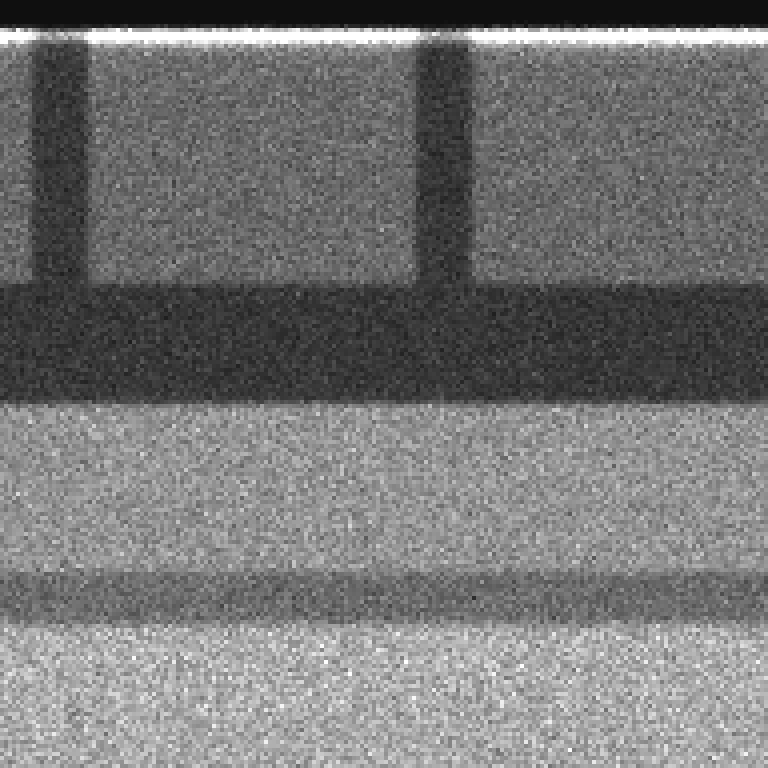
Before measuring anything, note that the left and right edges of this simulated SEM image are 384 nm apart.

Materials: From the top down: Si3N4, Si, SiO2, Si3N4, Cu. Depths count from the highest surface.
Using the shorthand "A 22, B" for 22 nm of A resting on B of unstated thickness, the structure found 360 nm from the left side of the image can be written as Si3N4 126, Si 60, SiO2 84, Si3N4 26, Cu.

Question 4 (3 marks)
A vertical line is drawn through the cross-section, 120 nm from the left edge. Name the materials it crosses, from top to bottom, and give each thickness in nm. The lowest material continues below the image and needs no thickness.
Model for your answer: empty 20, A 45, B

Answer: Si3N4 126, Si 60, SiO2 84, Si3N4 26, Cu